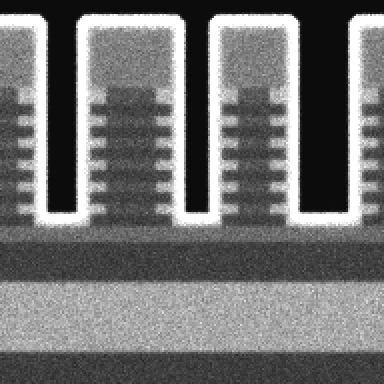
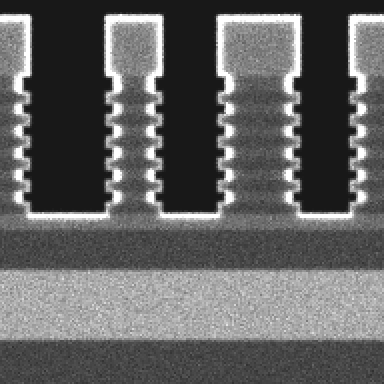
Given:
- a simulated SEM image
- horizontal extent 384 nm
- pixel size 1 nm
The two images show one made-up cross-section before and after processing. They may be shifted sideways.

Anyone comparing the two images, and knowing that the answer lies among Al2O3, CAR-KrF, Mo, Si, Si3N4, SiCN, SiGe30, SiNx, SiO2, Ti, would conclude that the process removed Al2O3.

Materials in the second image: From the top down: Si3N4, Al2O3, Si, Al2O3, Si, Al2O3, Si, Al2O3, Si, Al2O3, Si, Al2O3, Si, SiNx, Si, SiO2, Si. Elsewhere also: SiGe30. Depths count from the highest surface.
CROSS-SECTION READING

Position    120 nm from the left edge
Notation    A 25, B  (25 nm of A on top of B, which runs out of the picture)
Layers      Si3N4 60, Al2O3 16, Si 12, Al2O3 10, Si 12, Al2O3 10, Si 12, Al2O3 10, Si 12, Al2O3 10, Si 12, Al2O3 10, Si 12, SiNx 16, Si 40, SiO2 70, Si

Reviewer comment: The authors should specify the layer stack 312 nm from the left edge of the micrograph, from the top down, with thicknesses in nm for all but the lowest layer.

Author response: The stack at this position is empty 198, SiNx 16, Si 40, SiO2 70, Si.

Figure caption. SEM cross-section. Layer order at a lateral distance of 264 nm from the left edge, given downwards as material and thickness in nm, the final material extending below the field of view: Si3N4 60, SiGe30 16, Si 12, SiGe30 10, Si 12, SiGe30 10, Si 12, SiGe30 10, Si 12, SiGe30 10, Si 12, SiGe30 10, Si 12, SiNx 16, Si 40, SiO2 70, Si